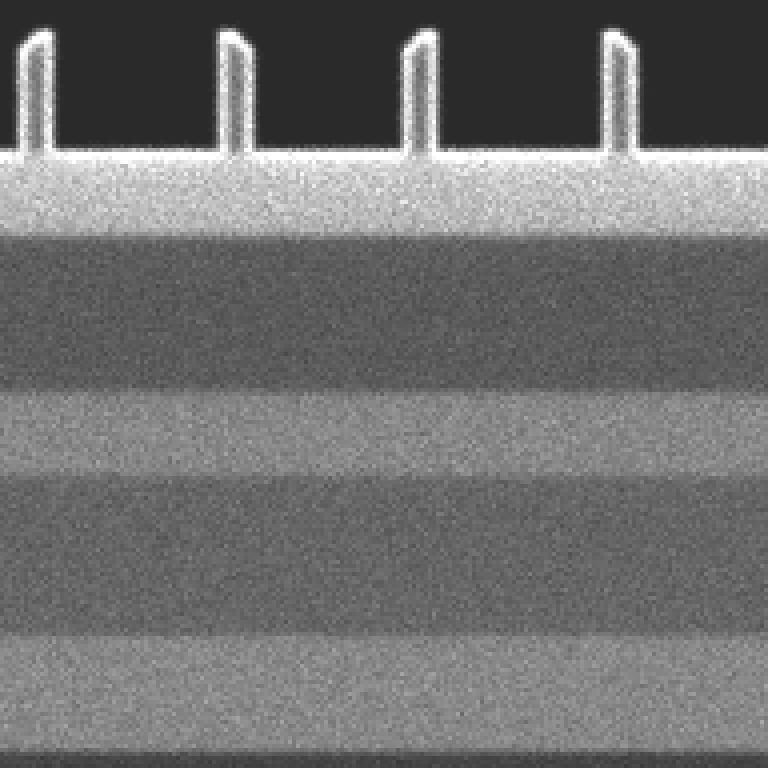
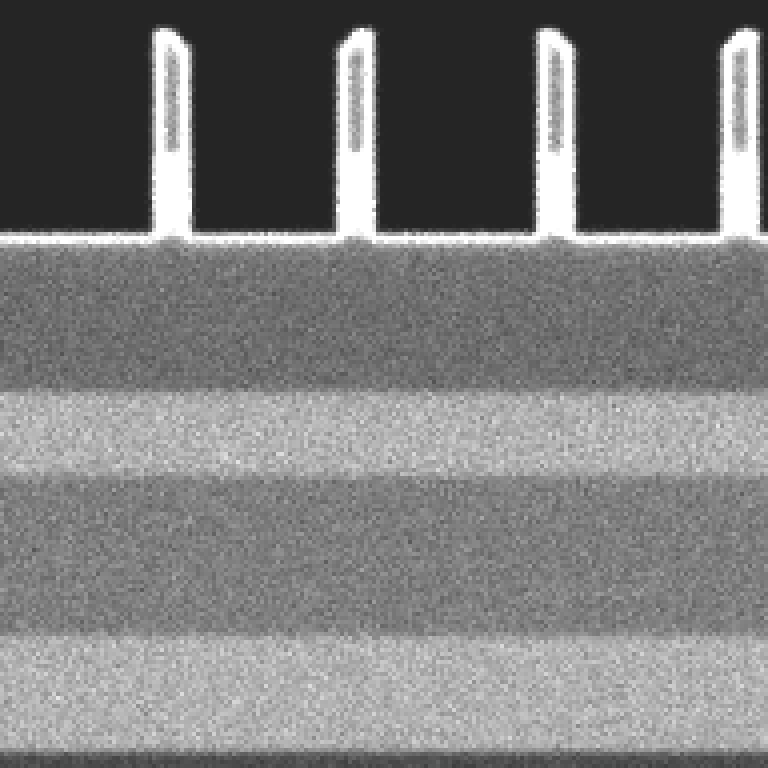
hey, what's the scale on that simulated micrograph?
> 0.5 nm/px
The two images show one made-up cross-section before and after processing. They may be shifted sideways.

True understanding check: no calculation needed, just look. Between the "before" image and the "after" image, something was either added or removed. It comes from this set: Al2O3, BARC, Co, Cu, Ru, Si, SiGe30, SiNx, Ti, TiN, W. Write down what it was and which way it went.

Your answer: W (removed)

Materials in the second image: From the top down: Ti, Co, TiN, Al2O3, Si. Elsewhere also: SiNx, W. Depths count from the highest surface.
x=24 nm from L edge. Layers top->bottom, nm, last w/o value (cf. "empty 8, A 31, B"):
empty 102, Ti 78, Co 42, TiN 80, Al2O3 58, Si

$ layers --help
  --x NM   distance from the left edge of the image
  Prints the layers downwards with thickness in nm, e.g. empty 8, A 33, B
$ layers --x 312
empty 102, Ti 78, Co 42, TiN 80, Al2O3 58, Si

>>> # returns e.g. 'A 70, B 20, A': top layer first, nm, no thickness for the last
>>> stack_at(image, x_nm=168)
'empty 102, Ti 78, Co 42, TiN 80, Al2O3 58, Si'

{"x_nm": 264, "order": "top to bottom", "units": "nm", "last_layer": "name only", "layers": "empty 102, Ti 78, Co 42, TiN 80, Al2O3 58, Si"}